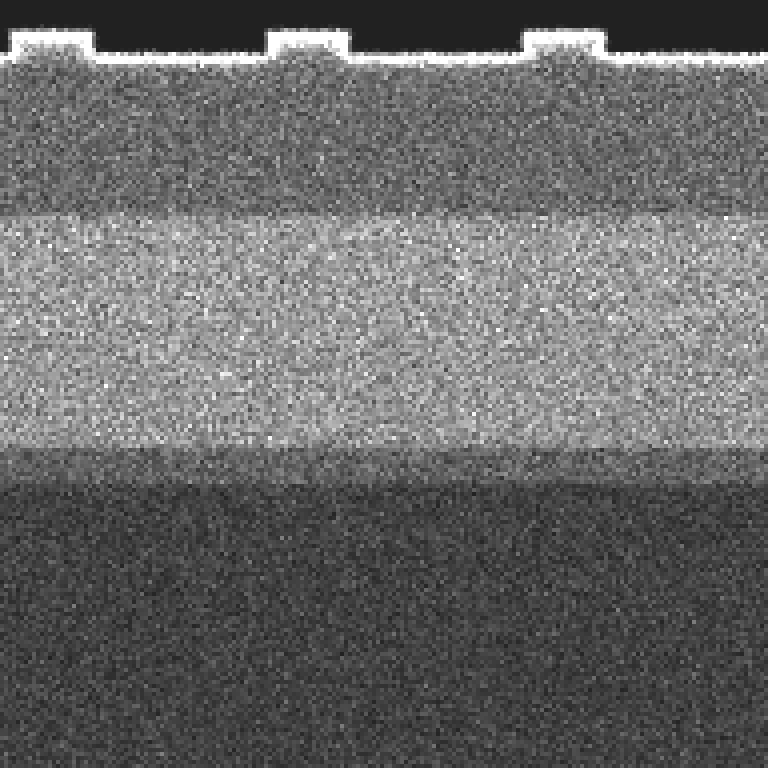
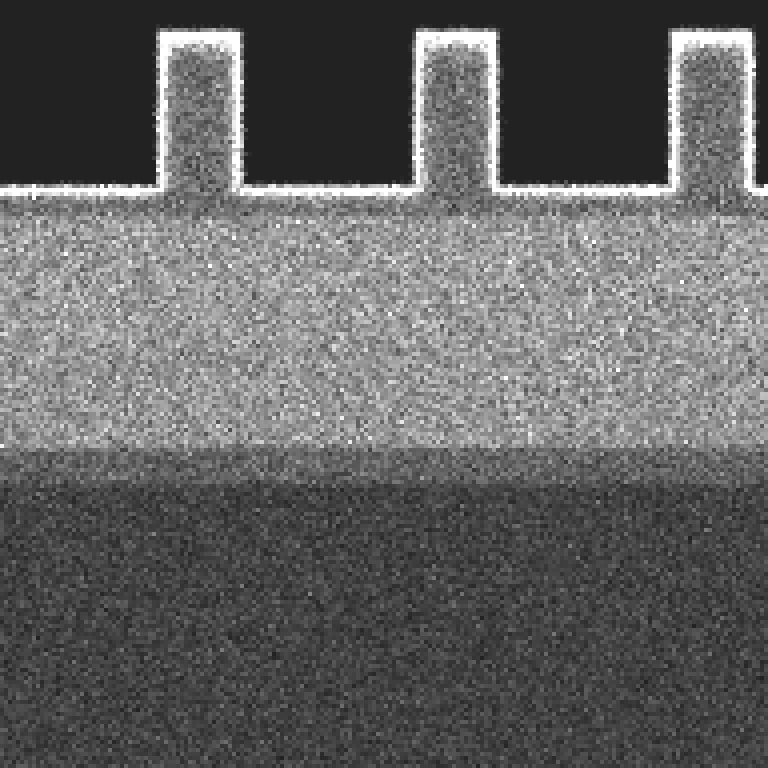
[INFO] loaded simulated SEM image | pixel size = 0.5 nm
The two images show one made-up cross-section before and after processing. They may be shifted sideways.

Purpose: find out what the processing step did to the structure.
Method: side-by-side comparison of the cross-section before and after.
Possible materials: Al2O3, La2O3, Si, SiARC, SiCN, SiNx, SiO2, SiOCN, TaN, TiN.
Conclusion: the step removed TiN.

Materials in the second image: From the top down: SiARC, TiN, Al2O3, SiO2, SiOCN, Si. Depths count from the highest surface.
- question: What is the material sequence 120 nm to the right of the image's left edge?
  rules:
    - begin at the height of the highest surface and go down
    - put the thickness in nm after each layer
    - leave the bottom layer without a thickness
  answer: empty 78, TiN 14, Al2O3 64, SiO2 52, SiOCN 18, Si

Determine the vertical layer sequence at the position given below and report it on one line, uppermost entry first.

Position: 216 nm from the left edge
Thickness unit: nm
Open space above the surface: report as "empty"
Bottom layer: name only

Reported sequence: SiARC 12, TiN 80, Al2O3 64, SiO2 52, SiOCN 18, Si